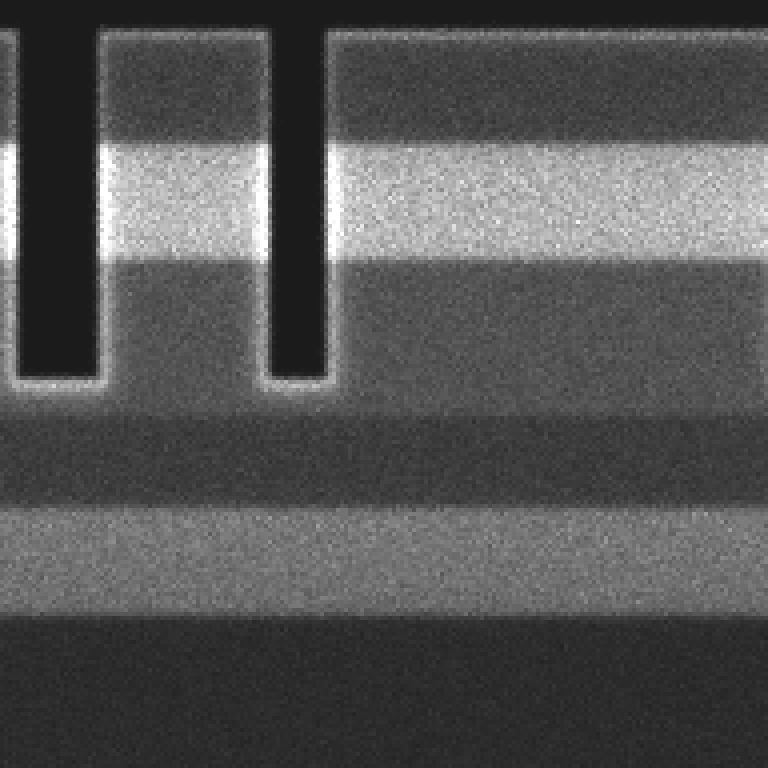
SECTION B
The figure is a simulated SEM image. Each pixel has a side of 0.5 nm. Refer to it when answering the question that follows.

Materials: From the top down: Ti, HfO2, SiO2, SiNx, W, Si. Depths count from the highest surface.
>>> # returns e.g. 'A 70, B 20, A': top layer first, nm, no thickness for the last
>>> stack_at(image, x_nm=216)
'Ti 56, HfO2 58, SiO2 78, SiNx 46, W 54, Si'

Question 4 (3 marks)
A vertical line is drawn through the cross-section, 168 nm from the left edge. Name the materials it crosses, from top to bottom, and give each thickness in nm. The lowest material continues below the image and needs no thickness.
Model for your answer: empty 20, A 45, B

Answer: Ti 56, HfO2 58, SiO2 78, SiNx 46, W 54, Si